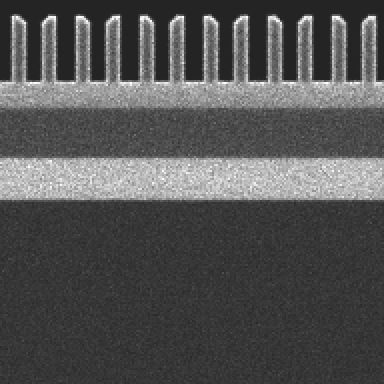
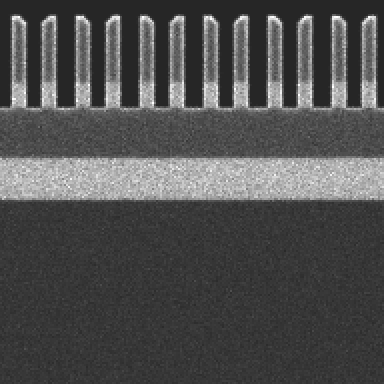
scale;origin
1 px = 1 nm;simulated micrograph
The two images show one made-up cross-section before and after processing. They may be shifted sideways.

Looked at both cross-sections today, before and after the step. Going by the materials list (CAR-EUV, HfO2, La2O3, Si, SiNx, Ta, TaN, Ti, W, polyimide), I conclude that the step removed W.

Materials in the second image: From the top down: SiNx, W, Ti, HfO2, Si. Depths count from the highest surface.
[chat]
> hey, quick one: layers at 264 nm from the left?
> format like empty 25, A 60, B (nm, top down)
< empty 92, Ti 50, HfO2 42, Si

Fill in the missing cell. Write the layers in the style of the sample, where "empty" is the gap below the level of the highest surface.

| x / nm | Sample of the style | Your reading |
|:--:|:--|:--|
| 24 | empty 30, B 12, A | empty 6, SiNx 60, W 26, Ti 50, HfO2 42, Si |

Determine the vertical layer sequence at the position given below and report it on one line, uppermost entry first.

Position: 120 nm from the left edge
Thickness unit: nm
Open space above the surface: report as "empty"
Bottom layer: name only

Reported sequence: empty 92, Ti 50, HfO2 42, Si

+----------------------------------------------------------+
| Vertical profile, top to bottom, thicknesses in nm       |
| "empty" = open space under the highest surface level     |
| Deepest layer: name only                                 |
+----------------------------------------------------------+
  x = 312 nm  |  empty 92, Ti 50, HfO2 42, Si